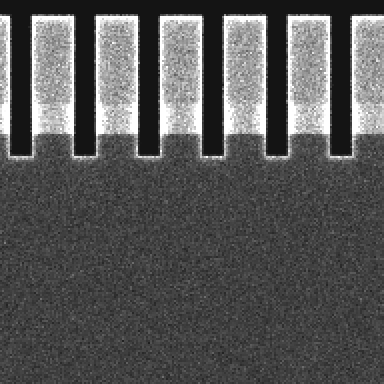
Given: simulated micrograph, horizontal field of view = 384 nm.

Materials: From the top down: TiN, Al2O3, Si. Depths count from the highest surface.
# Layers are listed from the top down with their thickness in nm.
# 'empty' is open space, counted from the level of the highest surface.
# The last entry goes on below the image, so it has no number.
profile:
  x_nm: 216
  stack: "empty 140, Si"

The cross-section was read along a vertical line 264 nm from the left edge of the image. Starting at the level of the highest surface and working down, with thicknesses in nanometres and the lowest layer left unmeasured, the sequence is TiN 88, Al2O3 30, Si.